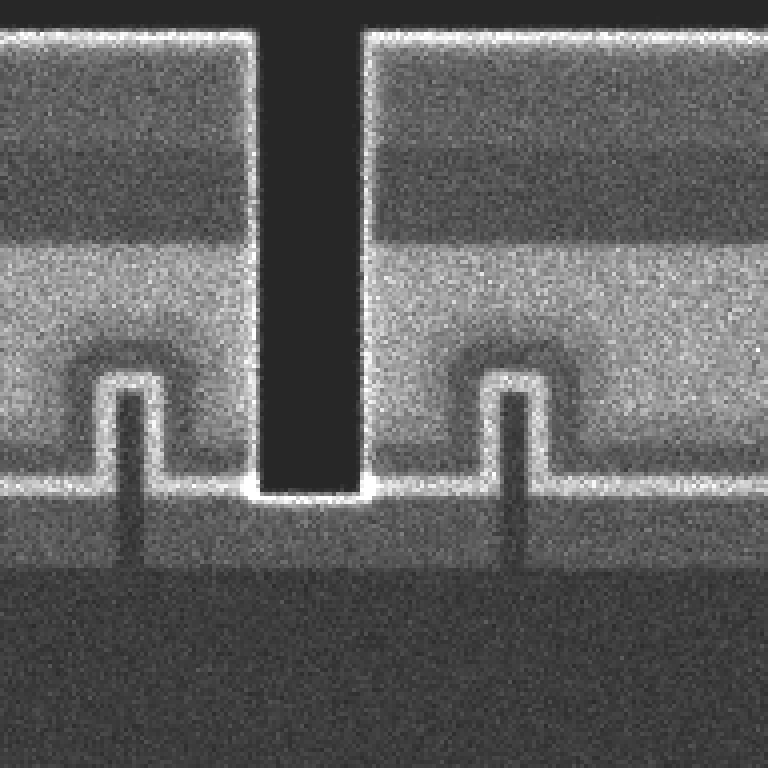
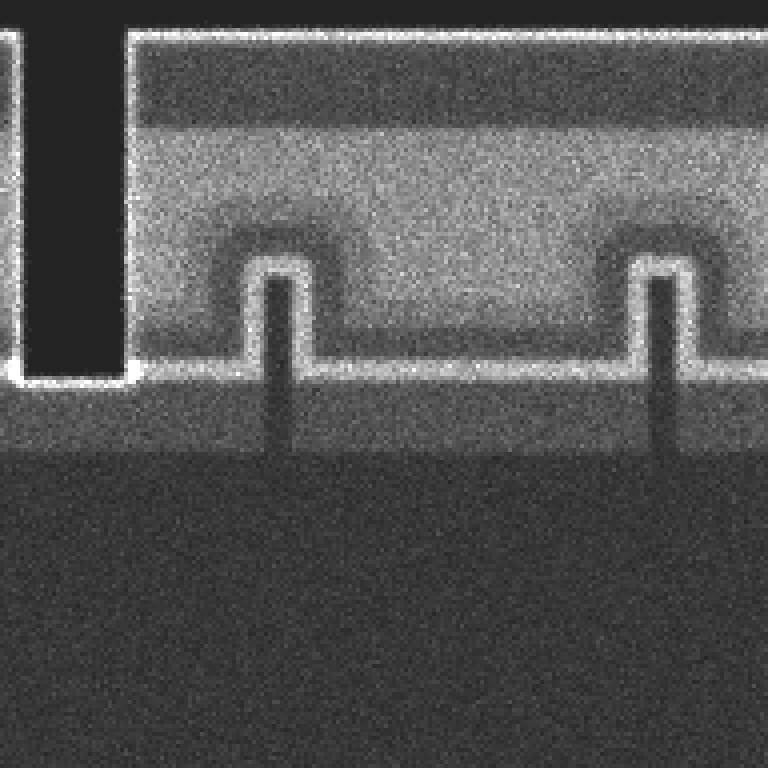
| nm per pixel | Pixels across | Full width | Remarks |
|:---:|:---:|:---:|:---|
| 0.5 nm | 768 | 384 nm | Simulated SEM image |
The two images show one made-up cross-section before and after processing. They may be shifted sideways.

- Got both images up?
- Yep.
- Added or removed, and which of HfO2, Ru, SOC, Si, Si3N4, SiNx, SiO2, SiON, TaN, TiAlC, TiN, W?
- removed, SOC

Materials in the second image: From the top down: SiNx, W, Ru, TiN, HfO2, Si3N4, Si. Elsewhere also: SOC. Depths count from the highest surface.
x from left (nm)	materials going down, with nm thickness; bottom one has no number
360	SiNx 48, W 36, Ru 22, TiN 58, HfO2 10, Si3N4 36, Si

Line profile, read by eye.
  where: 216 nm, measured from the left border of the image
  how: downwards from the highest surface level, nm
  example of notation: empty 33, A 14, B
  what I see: SiNx 48, W 86, Ru 14, TiN 16, HfO2 10, Si3N4 36, Si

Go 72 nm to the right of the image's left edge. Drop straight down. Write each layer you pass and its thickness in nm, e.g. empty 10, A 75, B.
SiNx 48, W 86, Ru 14, TiN 16, HfO2 10, Si3N4 36, Si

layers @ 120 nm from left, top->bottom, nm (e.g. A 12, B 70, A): SiNx 48, W 34, Ru 14, TiN 68, HfO2 10, Si3N4 36, Si